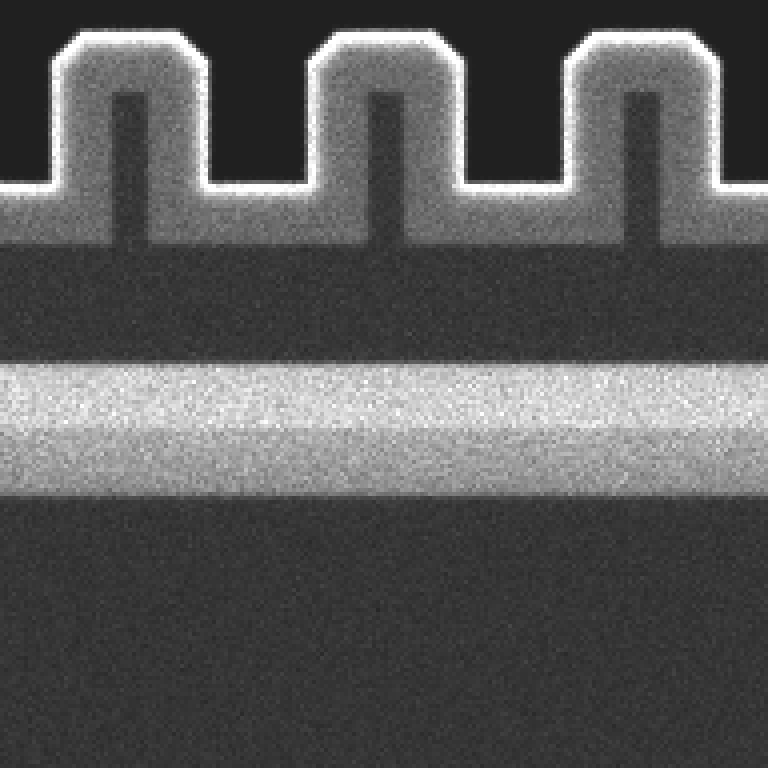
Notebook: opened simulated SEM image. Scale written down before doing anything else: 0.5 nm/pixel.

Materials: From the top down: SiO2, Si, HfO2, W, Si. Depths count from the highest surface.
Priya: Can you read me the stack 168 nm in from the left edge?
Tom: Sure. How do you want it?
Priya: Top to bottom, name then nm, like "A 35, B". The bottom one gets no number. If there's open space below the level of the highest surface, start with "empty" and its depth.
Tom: SiO2 106, Si 60, HfO2 32, W 34, Si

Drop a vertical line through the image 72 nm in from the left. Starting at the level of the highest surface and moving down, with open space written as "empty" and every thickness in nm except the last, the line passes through SiO2 30, Si 136, HfO2 32, W 34, Si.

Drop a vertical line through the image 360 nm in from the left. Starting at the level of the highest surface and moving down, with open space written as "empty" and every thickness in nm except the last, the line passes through empty 76, SiO2 30, Si 60, HfO2 32, W 34, Si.